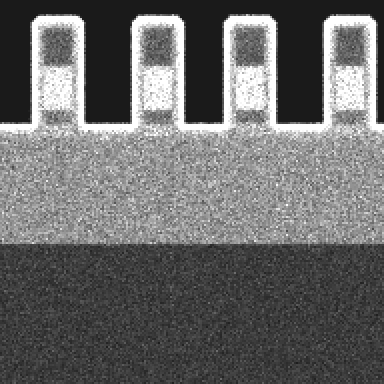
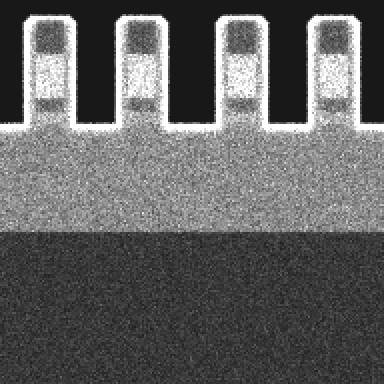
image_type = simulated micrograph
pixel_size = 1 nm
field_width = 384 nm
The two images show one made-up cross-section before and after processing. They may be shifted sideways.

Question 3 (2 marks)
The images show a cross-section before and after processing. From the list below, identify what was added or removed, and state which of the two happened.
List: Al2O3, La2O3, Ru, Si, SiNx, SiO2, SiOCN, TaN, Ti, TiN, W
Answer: SiO2 was removed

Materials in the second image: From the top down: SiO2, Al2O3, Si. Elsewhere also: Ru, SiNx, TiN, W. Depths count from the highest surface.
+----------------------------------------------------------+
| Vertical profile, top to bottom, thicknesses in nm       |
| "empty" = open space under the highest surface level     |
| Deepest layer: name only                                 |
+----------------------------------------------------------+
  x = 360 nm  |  empty 108, Al2O3 108, Si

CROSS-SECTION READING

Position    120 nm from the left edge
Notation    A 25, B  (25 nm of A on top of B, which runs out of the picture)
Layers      empty 2, SiO2 106, Al2O3 108, Si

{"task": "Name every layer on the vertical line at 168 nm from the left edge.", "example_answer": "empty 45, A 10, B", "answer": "empty 108, Al2O3 108, Si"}